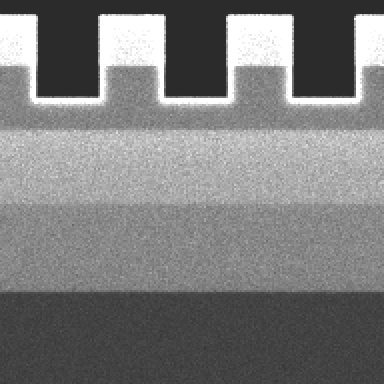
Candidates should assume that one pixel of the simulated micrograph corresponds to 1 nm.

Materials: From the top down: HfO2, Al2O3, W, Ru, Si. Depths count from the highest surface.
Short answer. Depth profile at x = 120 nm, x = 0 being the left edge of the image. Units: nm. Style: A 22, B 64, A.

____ HfO2 50, Al2O3 64, W 74, Ru 88, Si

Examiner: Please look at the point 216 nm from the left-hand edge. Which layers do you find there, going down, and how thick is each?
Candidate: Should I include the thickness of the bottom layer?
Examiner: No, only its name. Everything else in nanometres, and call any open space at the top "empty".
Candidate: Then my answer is empty 82, Al2O3 32, W 74, Ru 88, Si